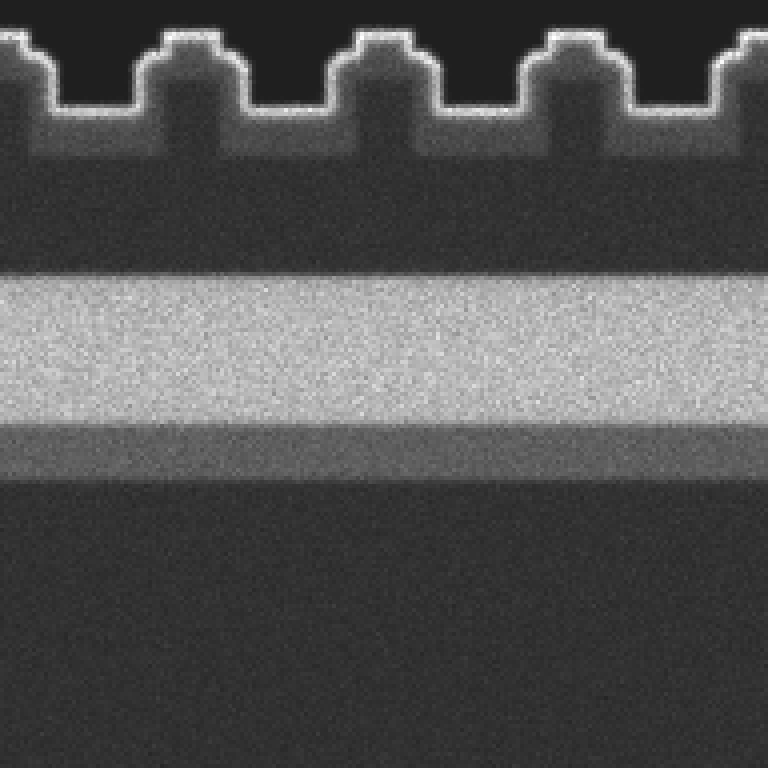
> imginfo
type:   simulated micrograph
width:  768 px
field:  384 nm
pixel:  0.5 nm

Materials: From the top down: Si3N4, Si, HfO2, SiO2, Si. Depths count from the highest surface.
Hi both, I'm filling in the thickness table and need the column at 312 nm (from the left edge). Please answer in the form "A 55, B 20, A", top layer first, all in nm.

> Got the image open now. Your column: empty 14, Si3N4 48, Si 60, HfO2 74, SiO2 28, Si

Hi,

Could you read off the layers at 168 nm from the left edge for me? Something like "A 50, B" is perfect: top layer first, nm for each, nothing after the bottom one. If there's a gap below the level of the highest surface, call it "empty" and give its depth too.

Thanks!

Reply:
empty 12, Si3N4 50, Si 60, HfO2 74, SiO2 28, Si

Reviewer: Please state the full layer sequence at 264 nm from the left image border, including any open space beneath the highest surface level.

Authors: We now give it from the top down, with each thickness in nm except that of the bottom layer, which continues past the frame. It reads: empty 12, Si3N4 50, Si 60, HfO2 74, SiO2 28, Si